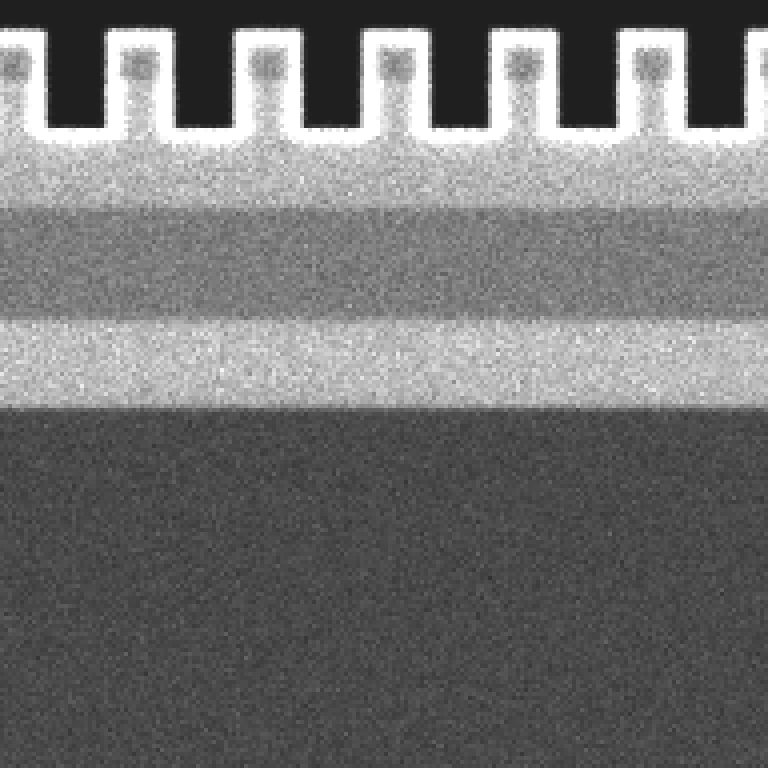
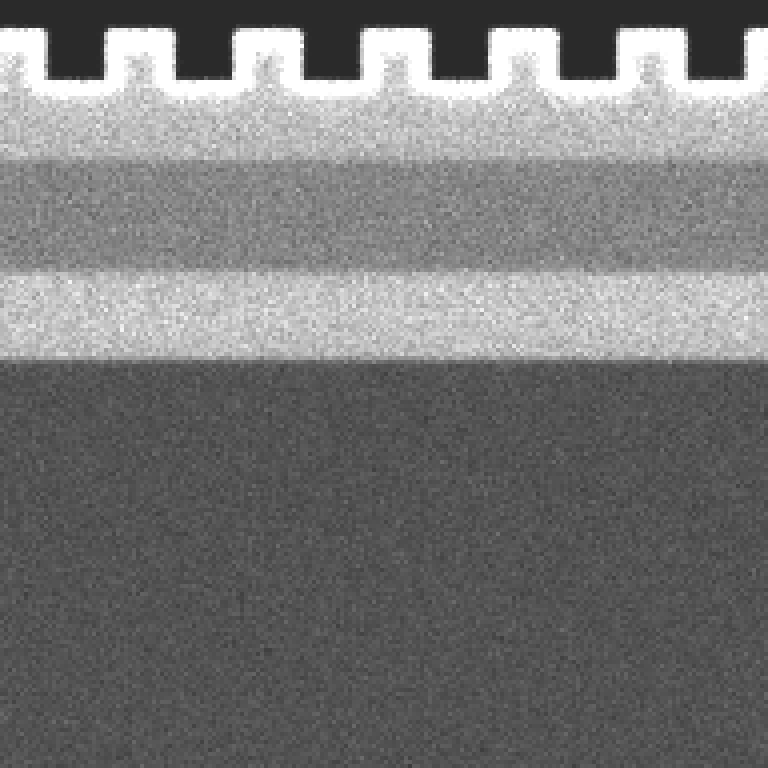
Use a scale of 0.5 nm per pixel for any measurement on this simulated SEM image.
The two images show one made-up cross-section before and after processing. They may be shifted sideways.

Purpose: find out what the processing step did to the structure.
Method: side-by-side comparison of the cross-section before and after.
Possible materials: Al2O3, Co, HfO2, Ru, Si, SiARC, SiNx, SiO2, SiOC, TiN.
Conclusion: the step removed SiARC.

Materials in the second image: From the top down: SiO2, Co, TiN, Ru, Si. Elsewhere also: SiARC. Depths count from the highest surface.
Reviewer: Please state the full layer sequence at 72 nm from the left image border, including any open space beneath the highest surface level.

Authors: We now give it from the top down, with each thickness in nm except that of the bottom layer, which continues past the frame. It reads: SiO2 26, Co 38, TiN 56, Ru 44, Si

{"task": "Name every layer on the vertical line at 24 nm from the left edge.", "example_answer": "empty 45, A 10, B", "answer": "empty 26, Co 38, TiN 56, Ru 44, Si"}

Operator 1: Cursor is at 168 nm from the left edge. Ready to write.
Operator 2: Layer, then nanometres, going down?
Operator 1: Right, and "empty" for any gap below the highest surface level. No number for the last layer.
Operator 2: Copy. empty 26, Co 38, TiN 56, Ru 44, Si